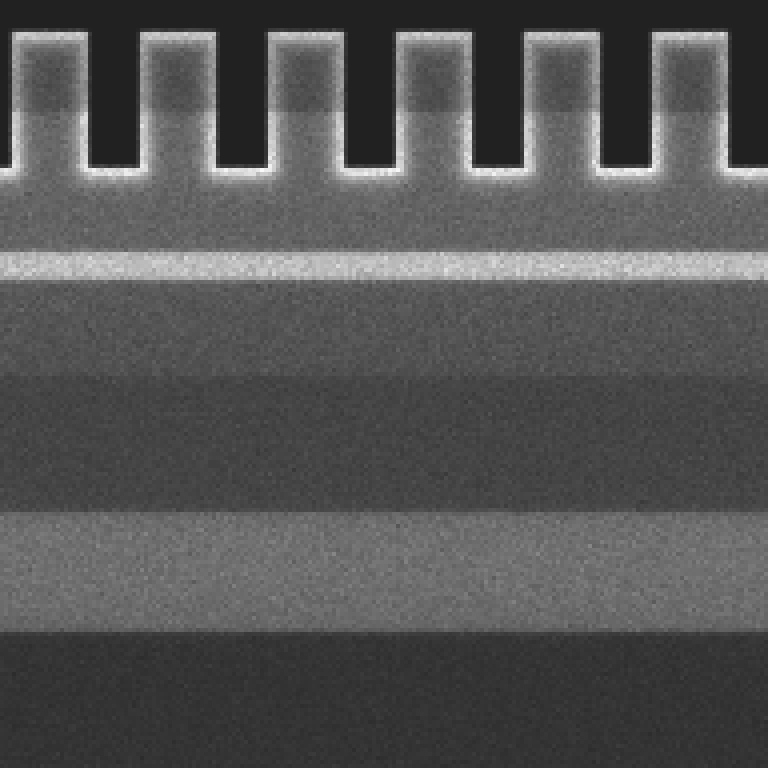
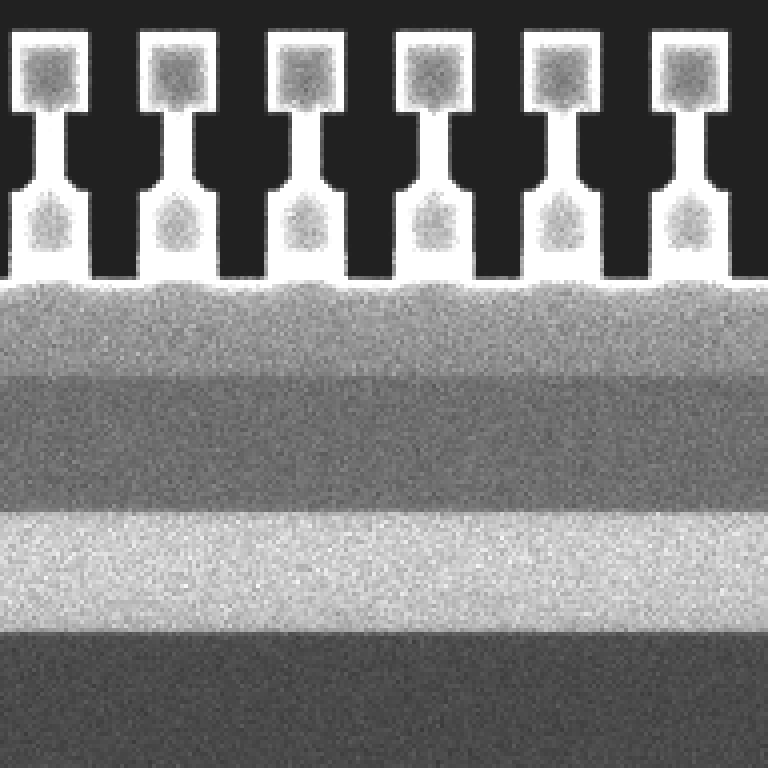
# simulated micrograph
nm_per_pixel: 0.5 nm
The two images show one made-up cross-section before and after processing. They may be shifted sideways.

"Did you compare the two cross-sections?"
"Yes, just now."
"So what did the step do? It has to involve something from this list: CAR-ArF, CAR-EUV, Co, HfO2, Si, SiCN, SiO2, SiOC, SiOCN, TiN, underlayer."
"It removed HfO2 and SiO2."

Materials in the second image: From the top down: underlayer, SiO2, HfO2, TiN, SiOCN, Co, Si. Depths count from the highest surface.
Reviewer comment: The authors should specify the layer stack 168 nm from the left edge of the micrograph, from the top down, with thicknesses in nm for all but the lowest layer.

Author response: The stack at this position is underlayer 40, empty 40, SiO2 30, HfO2 14, TiN 48, SiOCN 68, Co 60, Si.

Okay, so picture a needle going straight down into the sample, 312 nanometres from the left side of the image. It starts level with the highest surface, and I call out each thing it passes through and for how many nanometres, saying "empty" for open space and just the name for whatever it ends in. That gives empty 124, TiN 48, SiOCN 68, Co 60, Si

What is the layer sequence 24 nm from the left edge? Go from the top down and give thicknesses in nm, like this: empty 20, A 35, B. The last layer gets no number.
underlayer 40, SiO2 70, HfO2 14, TiN 48, SiOCN 68, Co 60, Si